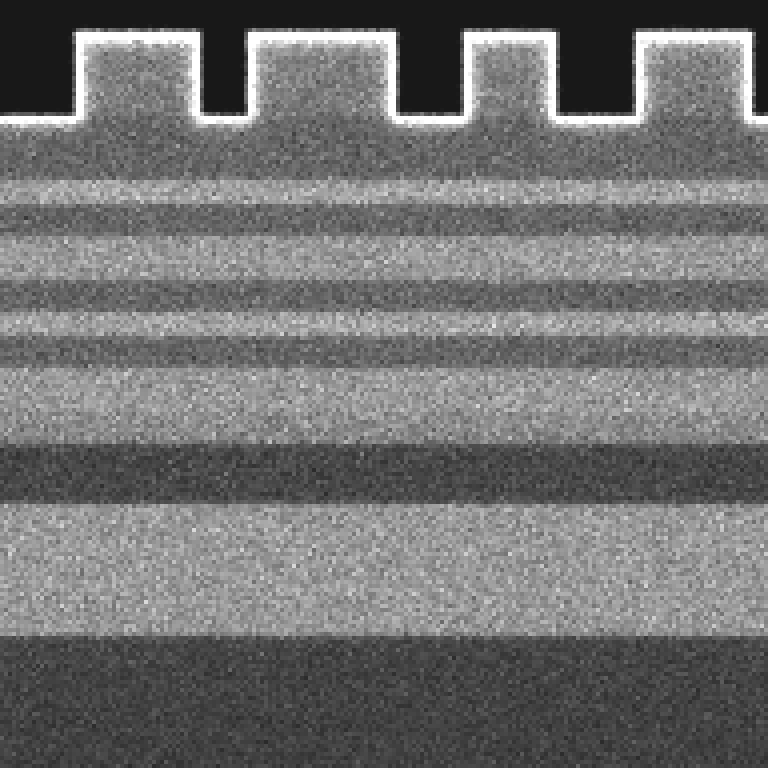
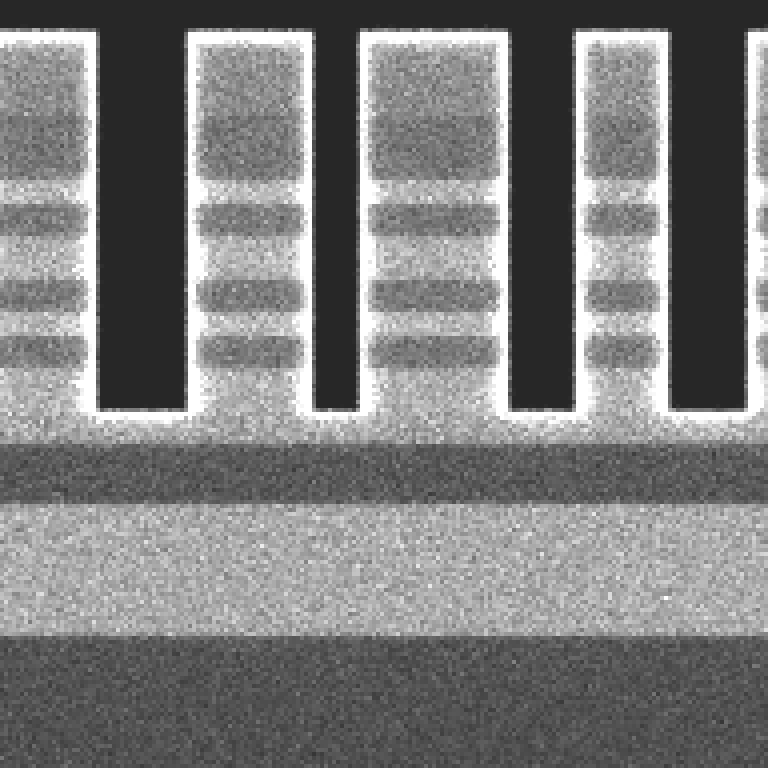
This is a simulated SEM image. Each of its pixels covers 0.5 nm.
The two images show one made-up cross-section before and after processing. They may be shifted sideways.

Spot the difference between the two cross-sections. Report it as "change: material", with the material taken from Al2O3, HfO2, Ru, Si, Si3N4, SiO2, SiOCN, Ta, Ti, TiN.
removed: Al2O3 and SiO2 and SiOCN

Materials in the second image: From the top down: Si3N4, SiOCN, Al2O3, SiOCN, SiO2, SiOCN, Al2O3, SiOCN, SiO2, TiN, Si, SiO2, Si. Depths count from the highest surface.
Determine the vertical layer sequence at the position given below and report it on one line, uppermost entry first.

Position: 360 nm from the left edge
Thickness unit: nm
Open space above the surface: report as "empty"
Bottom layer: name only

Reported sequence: empty 190, TiN 16, Si 30, SiO2 66, Si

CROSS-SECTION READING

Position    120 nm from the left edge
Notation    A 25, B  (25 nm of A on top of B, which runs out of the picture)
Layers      Si3N4 42, SiOCN 32, Al2O3 12, SiOCN 16, SiO2 22, SiOCN 16, Al2O3 12, SiOCN 16, SiO2 22, TiN 16, Si 30, SiO2 66, Si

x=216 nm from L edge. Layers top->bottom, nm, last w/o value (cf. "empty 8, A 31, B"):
Si3N4 42, SiOCN 32, Al2O3 12, SiOCN 16, SiO2 22, SiOCN 16, Al2O3 12, SiOCN 16, SiO2 22, TiN 16, Si 30, SiO2 66, Si